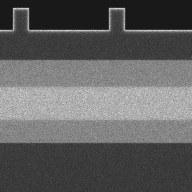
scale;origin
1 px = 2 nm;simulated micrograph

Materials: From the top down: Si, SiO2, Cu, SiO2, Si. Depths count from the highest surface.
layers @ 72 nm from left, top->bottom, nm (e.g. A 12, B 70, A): empty 44, Si 60, SiO2 54, Cu 66, SiO2 46, Si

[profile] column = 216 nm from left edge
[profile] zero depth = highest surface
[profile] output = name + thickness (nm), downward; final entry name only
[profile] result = empty 44, Si 60, SiO2 54, Cu 66, SiO2 46, Si